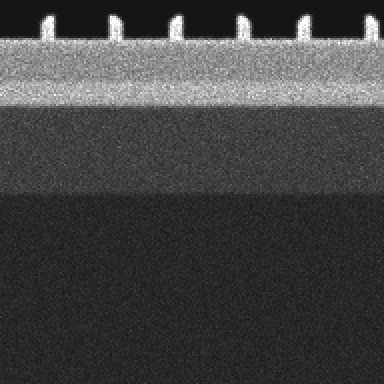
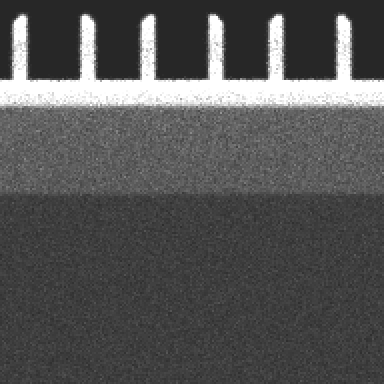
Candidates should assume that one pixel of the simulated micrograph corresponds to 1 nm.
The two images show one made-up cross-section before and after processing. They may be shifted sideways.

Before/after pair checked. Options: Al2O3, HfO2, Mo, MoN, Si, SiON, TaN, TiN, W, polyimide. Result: removed W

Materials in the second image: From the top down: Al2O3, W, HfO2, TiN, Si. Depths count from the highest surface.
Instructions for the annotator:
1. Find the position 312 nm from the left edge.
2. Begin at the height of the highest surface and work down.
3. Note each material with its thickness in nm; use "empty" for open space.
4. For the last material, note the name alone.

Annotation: empty 66, HfO2 24, TiN 88, Si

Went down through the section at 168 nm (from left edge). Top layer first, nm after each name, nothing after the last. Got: empty 66, HfO2 24, TiN 88, Si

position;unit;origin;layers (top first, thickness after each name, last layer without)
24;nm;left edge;Al2O3 24, W 42, HfO2 24, TiN 88, Si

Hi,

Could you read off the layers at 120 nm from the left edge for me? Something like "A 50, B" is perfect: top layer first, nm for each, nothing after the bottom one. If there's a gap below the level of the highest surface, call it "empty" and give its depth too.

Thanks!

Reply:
empty 66, HfO2 24, TiN 88, Si